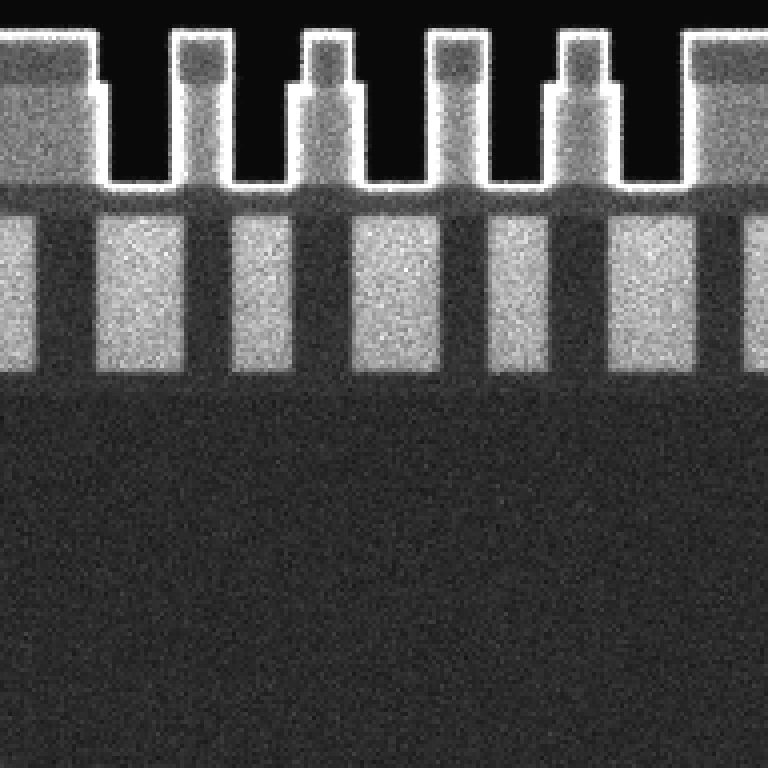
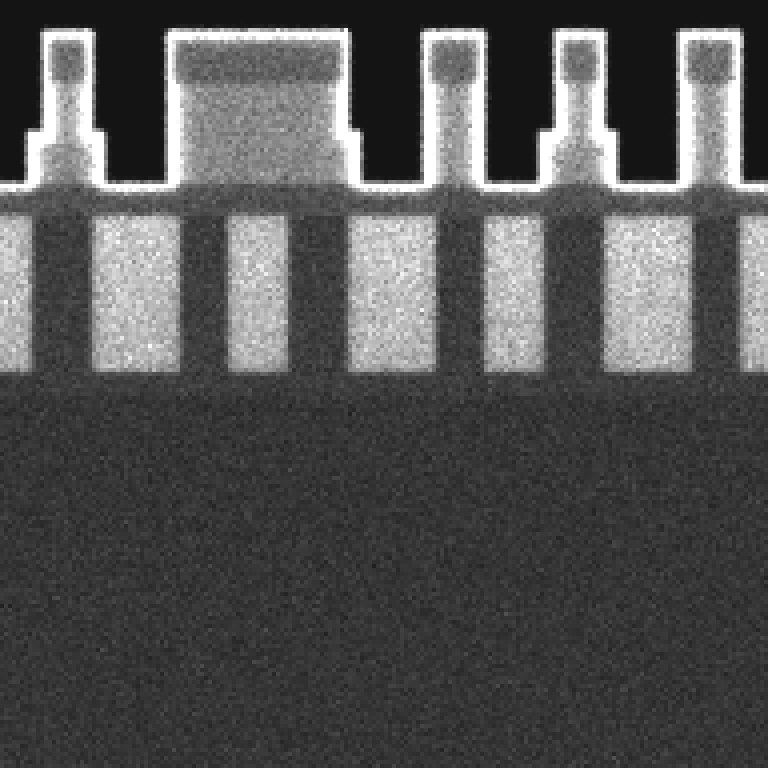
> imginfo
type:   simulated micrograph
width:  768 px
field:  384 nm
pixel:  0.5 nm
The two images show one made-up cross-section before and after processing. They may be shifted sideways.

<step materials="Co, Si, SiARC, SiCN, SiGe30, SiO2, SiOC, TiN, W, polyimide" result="removed SiO2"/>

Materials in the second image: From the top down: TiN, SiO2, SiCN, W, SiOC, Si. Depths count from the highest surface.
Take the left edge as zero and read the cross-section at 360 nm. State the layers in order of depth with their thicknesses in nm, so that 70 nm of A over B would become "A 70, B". TiN 26, SiO2 50, SiCN 16, SiOC 90, Si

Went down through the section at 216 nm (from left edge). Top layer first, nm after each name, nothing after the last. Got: TiN 26, SiO2 50, SiCN 16, W 78, SiOC 12, Si